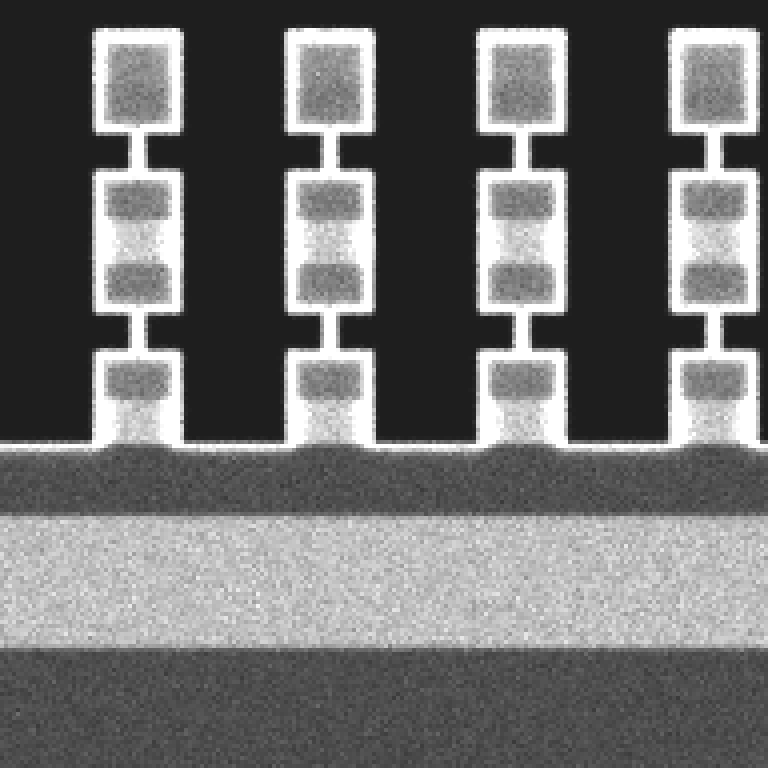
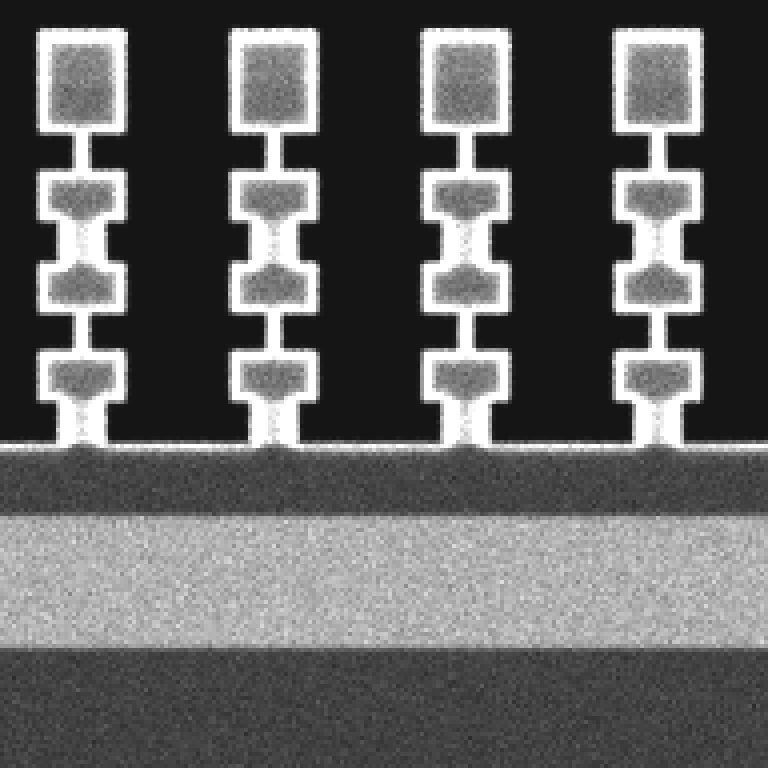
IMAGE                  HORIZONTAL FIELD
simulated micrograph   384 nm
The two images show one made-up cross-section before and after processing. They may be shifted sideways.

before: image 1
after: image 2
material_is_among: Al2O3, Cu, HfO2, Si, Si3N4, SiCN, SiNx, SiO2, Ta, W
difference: Al2O3, removed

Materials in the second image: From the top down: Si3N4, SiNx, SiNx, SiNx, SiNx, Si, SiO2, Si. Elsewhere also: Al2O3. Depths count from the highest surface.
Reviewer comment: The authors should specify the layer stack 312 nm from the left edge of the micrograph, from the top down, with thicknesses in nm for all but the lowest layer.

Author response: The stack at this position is Si3N4 26, SiNx 24, empty 20, SiNx 24, empty 22, SiNx 24, empty 20, SiNx 24, empty 22, Si 36, SiO2 66, Si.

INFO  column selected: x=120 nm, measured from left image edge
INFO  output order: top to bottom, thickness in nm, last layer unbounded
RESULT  Si3N4 26, SiNx 24, empty 20, SiNx 24, empty 22, SiNx 24, empty 20, SiNx 24, empty 22, Si 36, SiO2 66, Si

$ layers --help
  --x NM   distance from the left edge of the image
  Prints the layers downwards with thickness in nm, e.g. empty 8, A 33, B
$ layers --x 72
empty 206, Si 36, SiO2 66, Si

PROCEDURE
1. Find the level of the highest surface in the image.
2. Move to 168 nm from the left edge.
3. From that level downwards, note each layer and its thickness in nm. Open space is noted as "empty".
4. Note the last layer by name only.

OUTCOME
empty 206, Si 36, SiO2 66, Si